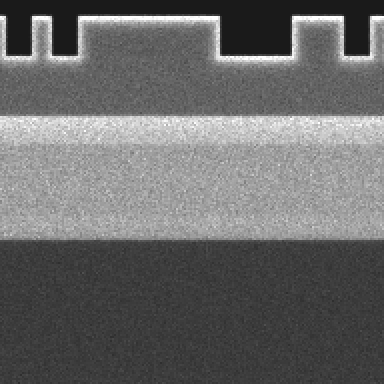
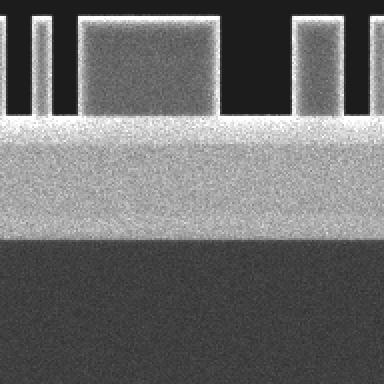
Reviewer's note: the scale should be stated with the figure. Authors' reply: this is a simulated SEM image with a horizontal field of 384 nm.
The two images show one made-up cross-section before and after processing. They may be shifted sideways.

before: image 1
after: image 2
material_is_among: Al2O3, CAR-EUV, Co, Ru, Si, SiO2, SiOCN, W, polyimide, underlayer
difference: underlayer, removed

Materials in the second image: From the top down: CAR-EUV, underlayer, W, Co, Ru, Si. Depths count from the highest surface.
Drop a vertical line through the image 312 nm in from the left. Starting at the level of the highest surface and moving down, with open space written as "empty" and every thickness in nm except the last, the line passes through CAR-EUV 40, underlayer 60, W 28, Co 72, Ru 24, Si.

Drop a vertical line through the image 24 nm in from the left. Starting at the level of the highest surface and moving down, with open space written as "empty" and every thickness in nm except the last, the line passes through empty 100, W 28, Co 72, Ru 24, Si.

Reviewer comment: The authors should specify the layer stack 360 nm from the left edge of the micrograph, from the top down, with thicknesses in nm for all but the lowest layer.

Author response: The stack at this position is empty 100, W 28, Co 72, Ru 24, Si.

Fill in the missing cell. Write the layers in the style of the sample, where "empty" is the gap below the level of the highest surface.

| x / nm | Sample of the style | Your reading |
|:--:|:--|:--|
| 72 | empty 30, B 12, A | empty 100, W 28, Co 72, Ru 24, Si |